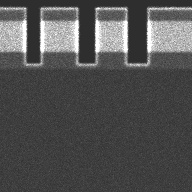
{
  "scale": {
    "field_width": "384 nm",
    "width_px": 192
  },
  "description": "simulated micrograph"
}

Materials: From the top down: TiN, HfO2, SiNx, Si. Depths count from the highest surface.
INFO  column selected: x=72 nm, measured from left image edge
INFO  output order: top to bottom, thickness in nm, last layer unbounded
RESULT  empty 112, SiNx 10, Si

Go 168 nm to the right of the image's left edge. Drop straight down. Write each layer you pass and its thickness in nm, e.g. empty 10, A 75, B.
empty 112, SiNx 10, Si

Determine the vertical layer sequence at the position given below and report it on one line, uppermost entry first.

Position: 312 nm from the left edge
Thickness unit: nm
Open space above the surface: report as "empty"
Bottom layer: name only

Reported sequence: TiN 26, HfO2 62, SiNx 34, Si